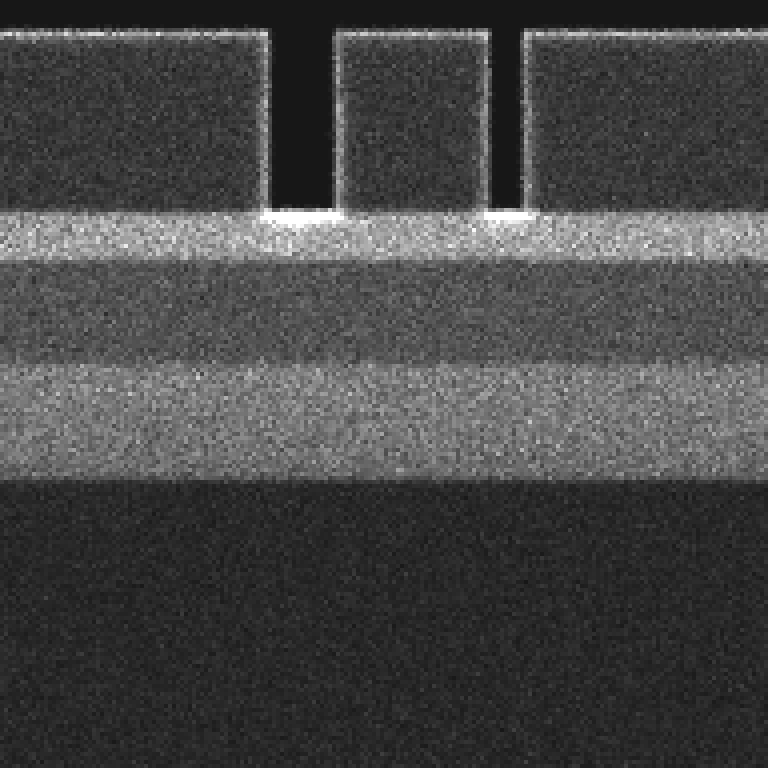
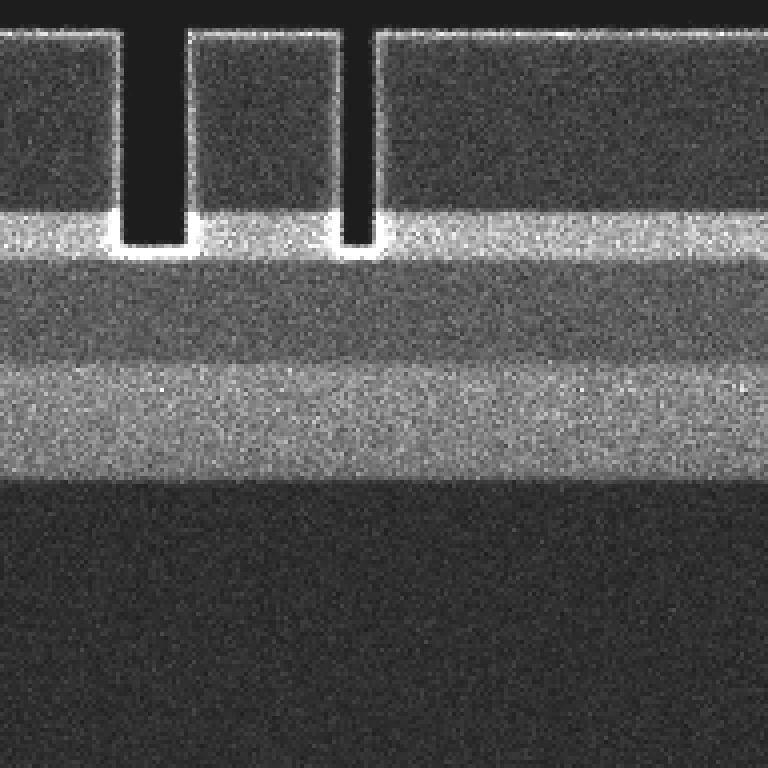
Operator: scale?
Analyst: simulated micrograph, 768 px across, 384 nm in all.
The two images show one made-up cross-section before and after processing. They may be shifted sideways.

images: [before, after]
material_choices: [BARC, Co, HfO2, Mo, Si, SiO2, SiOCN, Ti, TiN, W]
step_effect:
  removed: HfO2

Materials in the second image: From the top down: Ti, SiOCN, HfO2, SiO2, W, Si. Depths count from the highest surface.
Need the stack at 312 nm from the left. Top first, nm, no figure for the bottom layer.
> Ti 34, SiOCN 56, HfO2 24, SiO2 52, W 58, Si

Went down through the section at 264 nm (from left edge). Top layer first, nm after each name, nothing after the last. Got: Ti 34, SiOCN 56, HfO2 24, SiO2 52, W 58, Si